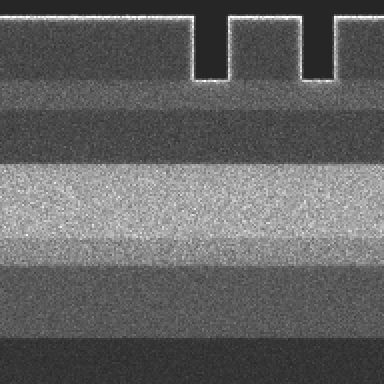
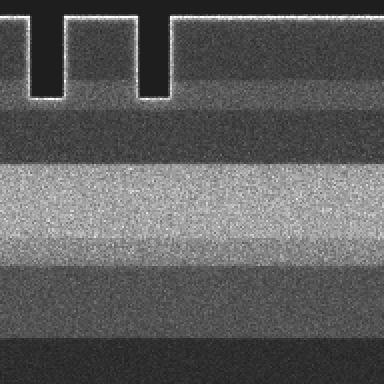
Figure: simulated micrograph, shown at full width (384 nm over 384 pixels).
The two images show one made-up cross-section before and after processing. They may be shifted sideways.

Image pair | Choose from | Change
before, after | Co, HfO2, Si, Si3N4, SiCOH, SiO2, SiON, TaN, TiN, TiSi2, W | Co (removed)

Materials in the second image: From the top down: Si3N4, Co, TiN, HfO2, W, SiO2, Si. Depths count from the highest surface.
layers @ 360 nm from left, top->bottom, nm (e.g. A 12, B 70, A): Si3N4 64, Co 30, TiN 54, HfO2 74, W 28, SiO2 72, Si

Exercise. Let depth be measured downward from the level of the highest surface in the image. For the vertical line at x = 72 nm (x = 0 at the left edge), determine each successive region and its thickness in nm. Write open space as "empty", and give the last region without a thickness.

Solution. Si3N4 64, Co 30, TiN 54, HfO2 74, W 28, SiO2 72, Si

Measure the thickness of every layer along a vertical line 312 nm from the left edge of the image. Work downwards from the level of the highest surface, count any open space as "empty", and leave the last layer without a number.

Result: Si3N4 64, Co 30, TiN 54, HfO2 74, W 28, SiO2 72, Si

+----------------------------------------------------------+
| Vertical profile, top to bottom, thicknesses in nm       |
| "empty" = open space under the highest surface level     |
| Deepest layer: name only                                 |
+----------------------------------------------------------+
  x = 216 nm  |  Si3N4 64, Co 30, TiN 54, HfO2 74, W 28, SiO2 72, Si